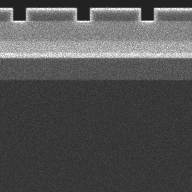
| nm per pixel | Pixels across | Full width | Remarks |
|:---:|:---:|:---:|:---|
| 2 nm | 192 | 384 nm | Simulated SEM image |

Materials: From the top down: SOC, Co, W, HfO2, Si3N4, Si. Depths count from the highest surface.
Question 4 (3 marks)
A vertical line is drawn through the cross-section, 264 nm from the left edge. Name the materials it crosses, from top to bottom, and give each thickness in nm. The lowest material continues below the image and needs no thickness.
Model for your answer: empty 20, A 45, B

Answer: SOC 26, Co 40, W 24, HfO2 10, Si3N4 44, Si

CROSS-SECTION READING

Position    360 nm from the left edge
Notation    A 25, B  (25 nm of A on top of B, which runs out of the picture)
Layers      SOC 26, Co 40, W 24, HfO2 10, Si3N4 44, Si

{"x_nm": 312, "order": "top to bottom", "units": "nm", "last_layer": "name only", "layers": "SOC 26, Co 40, W 24, HfO2 10, Si3N4 44, Si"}